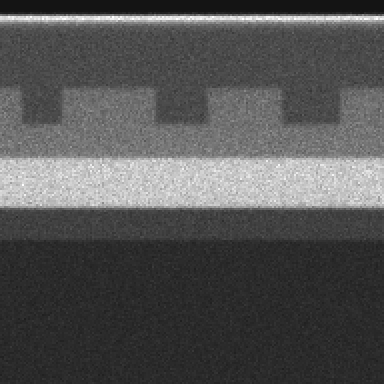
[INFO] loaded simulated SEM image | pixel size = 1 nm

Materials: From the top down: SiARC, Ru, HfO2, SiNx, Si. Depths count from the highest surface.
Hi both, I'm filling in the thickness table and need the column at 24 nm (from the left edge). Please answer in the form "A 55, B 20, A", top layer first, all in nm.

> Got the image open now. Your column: SiARC 108, Ru 34, HfO2 50, SiNx 32, Si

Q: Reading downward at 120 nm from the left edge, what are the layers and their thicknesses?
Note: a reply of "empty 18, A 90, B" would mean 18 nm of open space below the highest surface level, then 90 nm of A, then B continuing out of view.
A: SiARC 72, Ru 70, HfO2 50, SiNx 32, Si